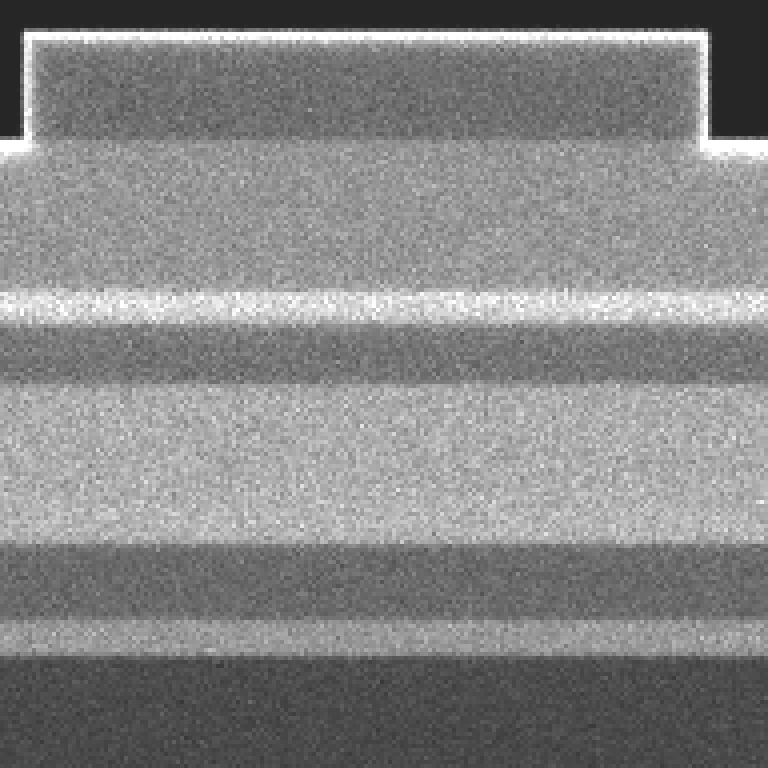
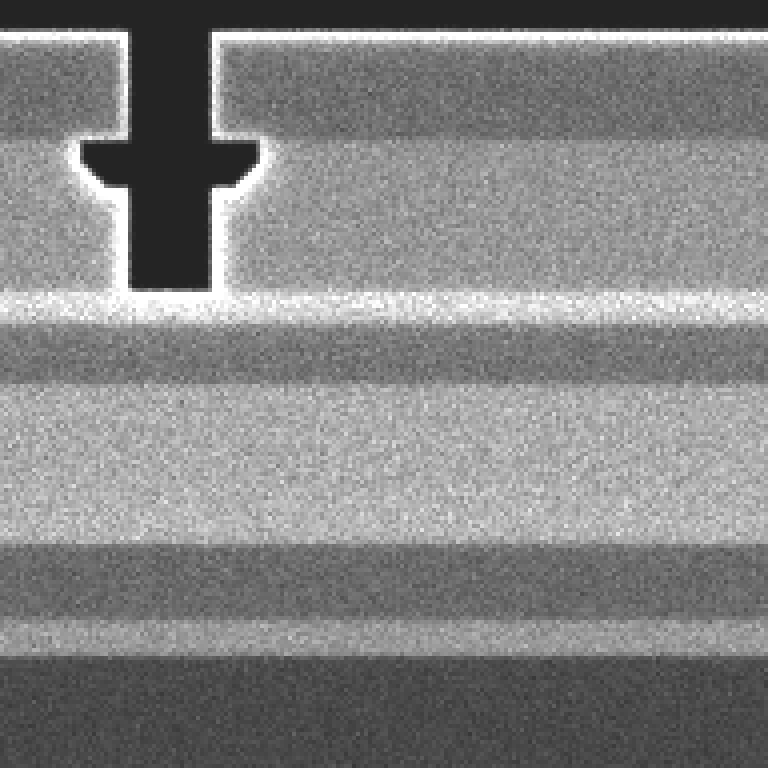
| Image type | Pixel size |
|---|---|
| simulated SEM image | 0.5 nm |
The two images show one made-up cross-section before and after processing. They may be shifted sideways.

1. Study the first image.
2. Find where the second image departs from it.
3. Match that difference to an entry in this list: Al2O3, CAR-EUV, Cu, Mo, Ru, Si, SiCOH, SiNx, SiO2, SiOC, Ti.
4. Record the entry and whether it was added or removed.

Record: SiO2 / removed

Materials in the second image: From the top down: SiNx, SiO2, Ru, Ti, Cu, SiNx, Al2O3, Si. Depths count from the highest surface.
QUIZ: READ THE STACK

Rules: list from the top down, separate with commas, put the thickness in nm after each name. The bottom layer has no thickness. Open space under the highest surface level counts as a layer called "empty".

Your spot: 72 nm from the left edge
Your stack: empty 130, Ru 16, Ti 30, Cu 80, SiNx 38, Al2O3 18, Si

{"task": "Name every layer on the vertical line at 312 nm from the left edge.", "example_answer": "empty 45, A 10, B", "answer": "SiNx 54, SiO2 76, Ru 16, Ti 30, Cu 80, SiNx 38, Al2O3 18, Si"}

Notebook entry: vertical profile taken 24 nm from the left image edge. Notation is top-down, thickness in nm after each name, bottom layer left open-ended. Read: SiNx 54, SiO2 76, Ru 16, Ti 30, Cu 80, SiNx 38, Al2O3 18, Si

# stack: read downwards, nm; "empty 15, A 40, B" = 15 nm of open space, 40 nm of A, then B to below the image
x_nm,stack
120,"SiNx 54, empty 20, SiO2 56, Ru 16, Ti 30, Cu 80, SiNx 38, Al2O3 18, Si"